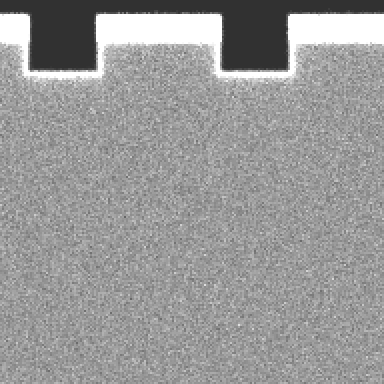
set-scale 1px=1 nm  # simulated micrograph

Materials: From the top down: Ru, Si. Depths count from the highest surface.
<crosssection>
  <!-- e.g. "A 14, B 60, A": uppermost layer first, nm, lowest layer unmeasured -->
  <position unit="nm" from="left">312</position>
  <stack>Ru 26, Si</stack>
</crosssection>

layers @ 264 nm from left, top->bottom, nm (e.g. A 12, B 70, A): empty 56, Si